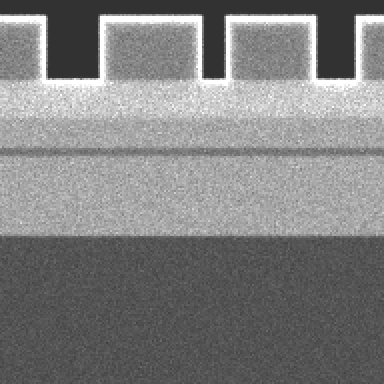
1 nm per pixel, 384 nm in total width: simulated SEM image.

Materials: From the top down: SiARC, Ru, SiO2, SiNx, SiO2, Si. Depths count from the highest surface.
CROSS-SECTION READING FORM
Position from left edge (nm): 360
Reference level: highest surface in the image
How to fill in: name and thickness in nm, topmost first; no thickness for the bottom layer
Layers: SiARC 64, Ru 38, SiO2 30, SiNx 8, SiO2 80, Si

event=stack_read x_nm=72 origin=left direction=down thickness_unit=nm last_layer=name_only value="empty 64, Ru 38, SiO2 30, SiNx 8, SiO2 80, Si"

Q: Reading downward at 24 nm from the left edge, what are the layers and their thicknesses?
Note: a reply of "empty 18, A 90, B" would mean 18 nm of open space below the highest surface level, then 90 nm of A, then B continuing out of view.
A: SiARC 64, Ru 38, SiO2 30, SiNx 8, SiO2 80, Si